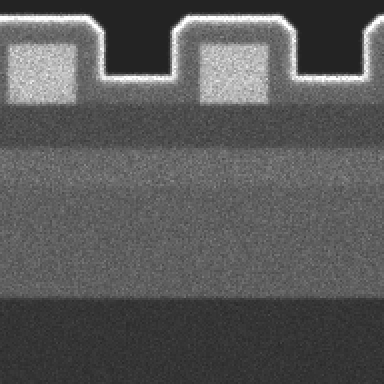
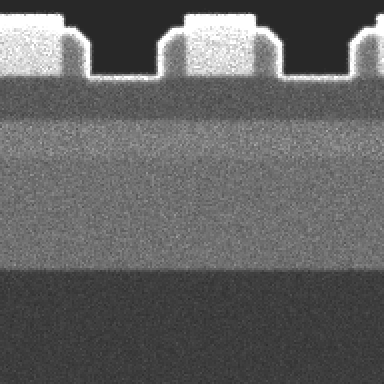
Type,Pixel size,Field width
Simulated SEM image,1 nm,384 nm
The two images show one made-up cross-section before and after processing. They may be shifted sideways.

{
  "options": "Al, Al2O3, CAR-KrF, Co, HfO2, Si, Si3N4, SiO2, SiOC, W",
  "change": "removed",
  "material": "Al2O3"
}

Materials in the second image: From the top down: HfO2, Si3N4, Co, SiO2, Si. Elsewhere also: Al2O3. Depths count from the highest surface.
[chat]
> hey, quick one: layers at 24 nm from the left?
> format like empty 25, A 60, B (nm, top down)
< HfO2 60, Si3N4 44, Co 38, SiO2 112, Si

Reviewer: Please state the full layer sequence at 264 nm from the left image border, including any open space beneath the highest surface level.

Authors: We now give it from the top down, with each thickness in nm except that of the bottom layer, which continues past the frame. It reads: empty 12, Al2O3 48, Si3N4 44, Co 38, SiO2 112, Si